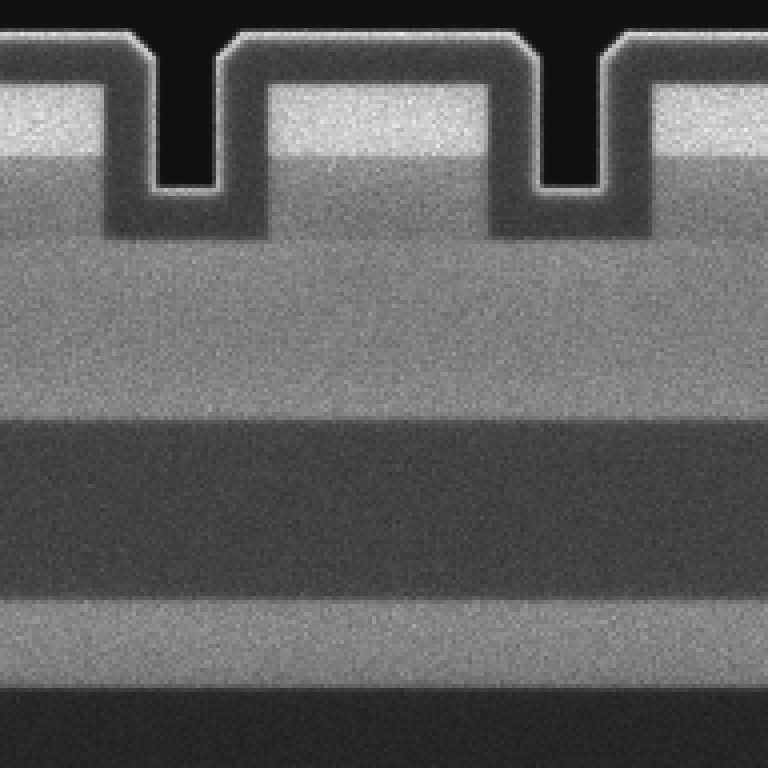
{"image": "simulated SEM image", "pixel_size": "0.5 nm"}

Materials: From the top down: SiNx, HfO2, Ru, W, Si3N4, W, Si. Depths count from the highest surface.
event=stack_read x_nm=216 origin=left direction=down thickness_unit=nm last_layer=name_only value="SiNx 26, HfO2 36, Ru 42, W 90, Si3N4 90, W 44, Si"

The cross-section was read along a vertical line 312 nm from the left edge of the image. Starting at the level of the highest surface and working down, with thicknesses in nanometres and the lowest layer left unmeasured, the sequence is SiNx 104, W 90, Si3N4 90, W 44, Si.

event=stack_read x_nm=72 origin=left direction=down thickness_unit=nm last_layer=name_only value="empty 8, SiNx 96, W 90, Si3N4 90, W 44, Si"